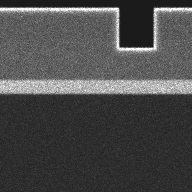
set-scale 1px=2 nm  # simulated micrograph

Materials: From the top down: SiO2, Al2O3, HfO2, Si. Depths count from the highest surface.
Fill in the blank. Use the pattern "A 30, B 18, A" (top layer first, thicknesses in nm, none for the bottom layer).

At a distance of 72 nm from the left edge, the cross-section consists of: SiO2 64, Al2O3 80, HfO2 28, Si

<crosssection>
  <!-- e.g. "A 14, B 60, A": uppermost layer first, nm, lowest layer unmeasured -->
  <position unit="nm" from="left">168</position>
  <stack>SiO2 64, Al2O3 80, HfO2 28, Si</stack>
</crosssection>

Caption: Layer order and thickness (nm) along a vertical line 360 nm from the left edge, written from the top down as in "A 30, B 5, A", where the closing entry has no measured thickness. SiO2 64, Al2O3 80, HfO2 28, Si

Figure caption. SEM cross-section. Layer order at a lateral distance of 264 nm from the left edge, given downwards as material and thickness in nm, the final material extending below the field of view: empty 80, Al2O3 64, HfO2 28, Si